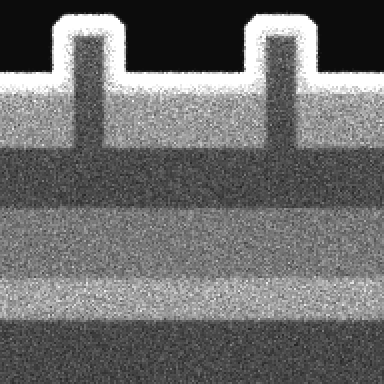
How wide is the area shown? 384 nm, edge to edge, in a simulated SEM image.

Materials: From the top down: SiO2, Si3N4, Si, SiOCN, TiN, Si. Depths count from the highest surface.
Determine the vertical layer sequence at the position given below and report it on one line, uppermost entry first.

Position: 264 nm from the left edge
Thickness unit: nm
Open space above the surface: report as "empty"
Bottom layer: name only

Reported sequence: SiO2 78, Si3N4 54, Si 60, SiOCN 70, TiN 42, Si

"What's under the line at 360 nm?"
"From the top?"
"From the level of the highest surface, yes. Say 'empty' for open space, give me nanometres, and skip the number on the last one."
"empty 58, SiO2 20, Si3N4 54, Si 60, SiOCN 70, TiN 42, Si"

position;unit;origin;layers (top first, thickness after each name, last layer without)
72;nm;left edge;SiO2 78, Si3N4 54, Si 60, SiOCN 70, TiN 42, Si